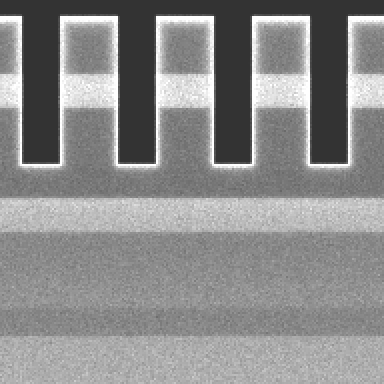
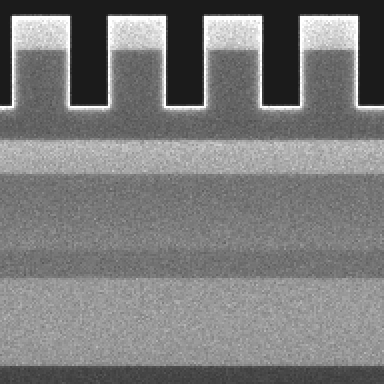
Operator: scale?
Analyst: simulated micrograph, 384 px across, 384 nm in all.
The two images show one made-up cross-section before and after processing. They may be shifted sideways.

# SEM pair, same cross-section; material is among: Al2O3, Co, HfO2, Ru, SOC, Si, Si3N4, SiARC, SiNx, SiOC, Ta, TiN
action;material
removed;SOC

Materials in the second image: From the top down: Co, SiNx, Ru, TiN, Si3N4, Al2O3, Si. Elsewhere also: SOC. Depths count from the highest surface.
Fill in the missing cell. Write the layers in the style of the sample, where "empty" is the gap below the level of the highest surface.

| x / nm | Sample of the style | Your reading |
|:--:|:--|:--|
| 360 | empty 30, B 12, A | empty 90, SiNx 34, Ru 34, TiN 76, Si3N4 28, Al2O3 88, Si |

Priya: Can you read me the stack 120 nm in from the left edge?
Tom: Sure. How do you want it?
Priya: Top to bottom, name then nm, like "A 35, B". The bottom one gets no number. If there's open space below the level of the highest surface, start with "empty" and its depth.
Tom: Co 34, SiNx 90, Ru 34, TiN 76, Si3N4 28, Al2O3 88, Si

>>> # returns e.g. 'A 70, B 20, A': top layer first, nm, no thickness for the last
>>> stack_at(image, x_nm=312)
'Co 34, SiNx 90, Ru 34, TiN 76, Si3N4 28, Al2O3 88, Si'